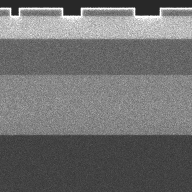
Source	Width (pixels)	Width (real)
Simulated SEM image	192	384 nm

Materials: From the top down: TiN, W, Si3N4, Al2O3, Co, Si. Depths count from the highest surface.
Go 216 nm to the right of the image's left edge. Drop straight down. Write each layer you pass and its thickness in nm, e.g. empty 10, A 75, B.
TiN 16, W 46, Si3N4 72, Al2O3 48, Co 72, Si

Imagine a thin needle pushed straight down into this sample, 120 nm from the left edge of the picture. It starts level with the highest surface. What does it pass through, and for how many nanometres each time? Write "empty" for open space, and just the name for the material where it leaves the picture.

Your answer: TiN 16, W 46, Si3N4 72, Al2O3 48, Co 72, Si